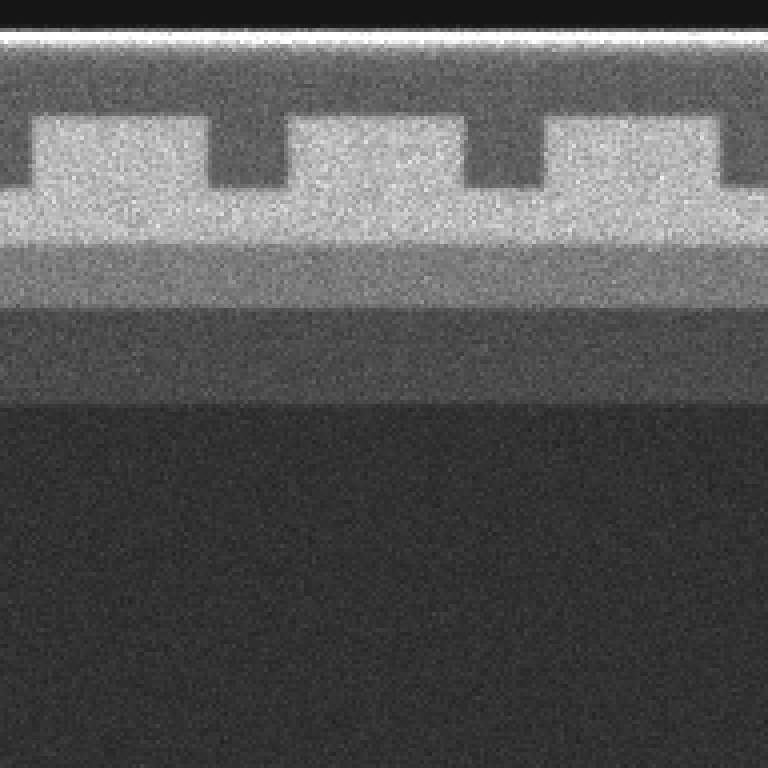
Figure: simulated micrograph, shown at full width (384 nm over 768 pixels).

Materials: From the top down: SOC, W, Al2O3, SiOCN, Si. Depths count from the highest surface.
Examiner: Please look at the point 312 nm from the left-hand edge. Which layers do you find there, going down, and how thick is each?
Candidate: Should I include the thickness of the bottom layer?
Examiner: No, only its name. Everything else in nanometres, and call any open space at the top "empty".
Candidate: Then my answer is SOC 42, W 64, Al2O3 32, SiOCN 48, Si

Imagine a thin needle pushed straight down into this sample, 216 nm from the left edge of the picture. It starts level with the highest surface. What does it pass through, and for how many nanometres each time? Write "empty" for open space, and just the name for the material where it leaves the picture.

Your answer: SOC 42, W 64, Al2O3 32, SiOCN 48, Si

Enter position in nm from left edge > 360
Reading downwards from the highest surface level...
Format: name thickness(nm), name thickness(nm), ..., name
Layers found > SOC 78, W 28, Al2O3 32, SiOCN 48, Si